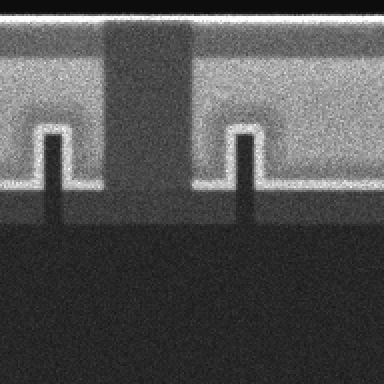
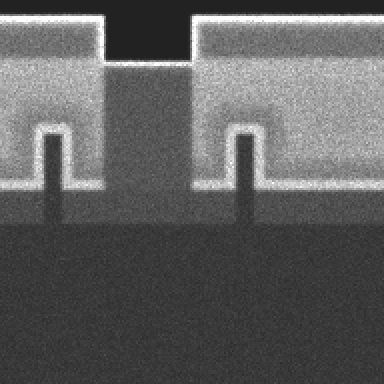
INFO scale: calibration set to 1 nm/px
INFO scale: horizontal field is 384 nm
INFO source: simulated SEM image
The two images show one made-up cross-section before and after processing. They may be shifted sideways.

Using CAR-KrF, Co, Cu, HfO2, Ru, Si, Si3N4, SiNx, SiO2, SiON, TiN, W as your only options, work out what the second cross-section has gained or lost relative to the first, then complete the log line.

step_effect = removed Si3N4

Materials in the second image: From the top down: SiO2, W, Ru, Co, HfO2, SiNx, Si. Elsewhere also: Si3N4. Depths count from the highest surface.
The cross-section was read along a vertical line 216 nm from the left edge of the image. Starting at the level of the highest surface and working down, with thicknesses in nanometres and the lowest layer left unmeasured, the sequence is SiO2 42, W 46, Ru 16, Co 60, HfO2 10, SiNx 34, Si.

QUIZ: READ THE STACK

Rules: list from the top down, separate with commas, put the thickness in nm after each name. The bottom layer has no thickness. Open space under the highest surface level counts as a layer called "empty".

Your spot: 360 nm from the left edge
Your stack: SiO2 42, W 100, Ru 10, Co 12, HfO2 10, SiNx 34, Si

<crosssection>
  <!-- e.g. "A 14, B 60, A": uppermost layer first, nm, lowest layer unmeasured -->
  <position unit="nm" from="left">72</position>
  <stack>SiO2 42, W 44, Ru 10, Co 68, HfO2 10, SiNx 34, Si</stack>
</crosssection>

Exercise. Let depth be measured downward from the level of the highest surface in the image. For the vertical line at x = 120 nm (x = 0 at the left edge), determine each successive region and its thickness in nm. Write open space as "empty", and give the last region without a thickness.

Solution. empty 46, Si3N4 128, SiNx 34, Si